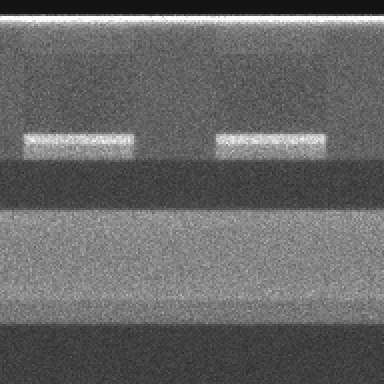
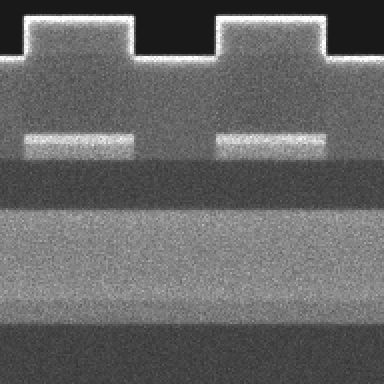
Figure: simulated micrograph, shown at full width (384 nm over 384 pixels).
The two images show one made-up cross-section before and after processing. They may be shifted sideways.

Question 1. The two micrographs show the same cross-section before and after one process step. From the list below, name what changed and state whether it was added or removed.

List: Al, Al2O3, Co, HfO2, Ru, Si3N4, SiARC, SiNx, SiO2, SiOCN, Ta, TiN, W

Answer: SiO2, removed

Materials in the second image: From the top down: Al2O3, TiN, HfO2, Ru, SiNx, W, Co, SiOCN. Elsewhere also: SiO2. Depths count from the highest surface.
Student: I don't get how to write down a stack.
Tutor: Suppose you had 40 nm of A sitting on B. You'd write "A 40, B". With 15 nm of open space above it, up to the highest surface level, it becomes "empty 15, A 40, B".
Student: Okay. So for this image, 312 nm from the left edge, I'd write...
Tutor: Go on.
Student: Al2O3 38, TiN 80, HfO2 10, Ru 16, SiNx 50, W 90, Co 24, SiOCN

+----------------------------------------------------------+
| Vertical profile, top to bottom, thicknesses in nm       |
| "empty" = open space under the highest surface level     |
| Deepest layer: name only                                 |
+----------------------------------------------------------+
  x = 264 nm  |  Al2O3 38, TiN 80, HfO2 10, Ru 16, SiNx 50, W 90, Co 24, SiOCN